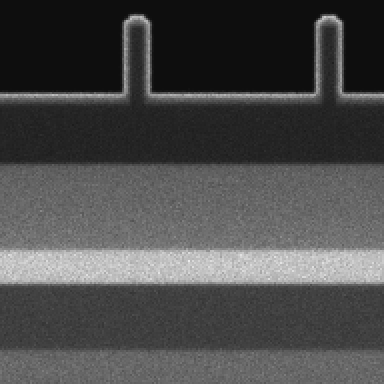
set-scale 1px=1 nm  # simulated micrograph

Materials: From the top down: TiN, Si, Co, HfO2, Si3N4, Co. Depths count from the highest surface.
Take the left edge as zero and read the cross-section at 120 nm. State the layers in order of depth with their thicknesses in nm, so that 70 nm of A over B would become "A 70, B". empty 78, TiN 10, Si 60, Co 86, HfO2 34, Si3N4 66, Co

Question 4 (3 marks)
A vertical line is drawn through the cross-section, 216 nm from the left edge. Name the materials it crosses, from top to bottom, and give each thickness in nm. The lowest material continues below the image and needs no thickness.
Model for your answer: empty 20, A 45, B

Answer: empty 78, TiN 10, Si 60, Co 86, HfO2 34, Si3N4 66, Co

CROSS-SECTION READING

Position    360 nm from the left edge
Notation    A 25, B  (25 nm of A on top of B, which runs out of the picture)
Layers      empty 78, TiN 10, Si 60, Co 86, HfO2 34, Si3N4 66, Co